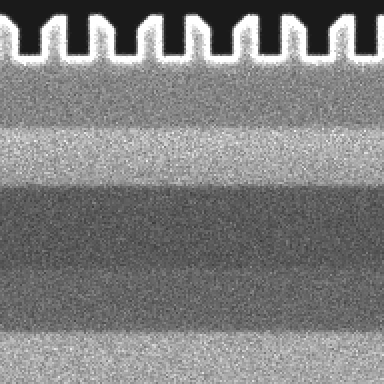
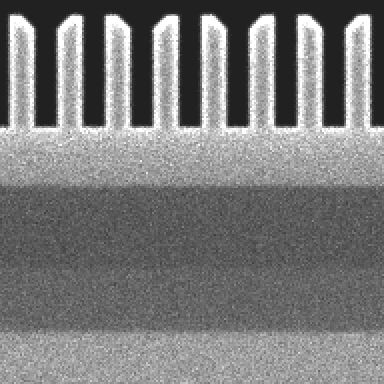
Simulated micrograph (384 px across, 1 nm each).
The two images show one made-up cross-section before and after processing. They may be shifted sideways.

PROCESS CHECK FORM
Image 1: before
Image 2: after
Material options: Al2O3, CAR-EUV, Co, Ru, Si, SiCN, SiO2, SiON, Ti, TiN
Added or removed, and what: removed, SiO2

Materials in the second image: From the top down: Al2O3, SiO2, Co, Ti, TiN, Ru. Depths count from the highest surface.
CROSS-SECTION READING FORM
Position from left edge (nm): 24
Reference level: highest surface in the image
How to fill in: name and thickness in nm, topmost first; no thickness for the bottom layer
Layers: empty 4, Al2O3 36, SiO2 72, Co 58, Ti 82, TiN 64, Ru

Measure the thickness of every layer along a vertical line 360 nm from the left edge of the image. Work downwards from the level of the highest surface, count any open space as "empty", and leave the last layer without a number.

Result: Al2O3 40, SiO2 72, Co 58, Ti 82, TiN 64, Ru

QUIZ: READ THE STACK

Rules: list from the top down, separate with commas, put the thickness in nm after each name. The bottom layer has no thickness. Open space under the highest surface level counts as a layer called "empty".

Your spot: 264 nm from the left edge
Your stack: Al2O3 40, SiO2 72, Co 58, Ti 82, TiN 64, Ru